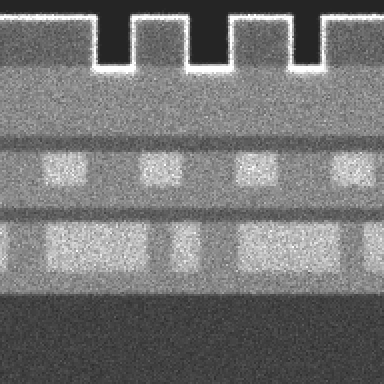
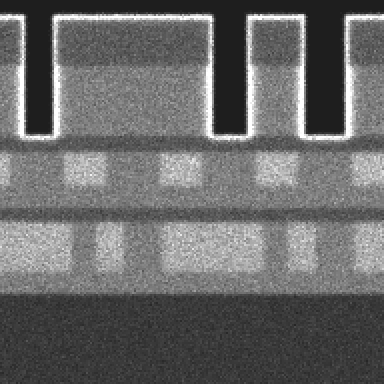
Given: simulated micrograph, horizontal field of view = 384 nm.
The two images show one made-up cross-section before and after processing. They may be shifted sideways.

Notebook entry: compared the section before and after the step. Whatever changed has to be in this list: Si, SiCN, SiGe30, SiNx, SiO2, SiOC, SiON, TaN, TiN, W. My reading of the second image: SiO2 removed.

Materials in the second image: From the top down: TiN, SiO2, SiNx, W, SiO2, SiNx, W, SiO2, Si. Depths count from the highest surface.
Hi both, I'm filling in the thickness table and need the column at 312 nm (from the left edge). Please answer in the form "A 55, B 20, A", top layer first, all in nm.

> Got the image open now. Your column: empty 120, SiNx 16, SiO2 56, SiNx 14, W 50, SiO2 22, Si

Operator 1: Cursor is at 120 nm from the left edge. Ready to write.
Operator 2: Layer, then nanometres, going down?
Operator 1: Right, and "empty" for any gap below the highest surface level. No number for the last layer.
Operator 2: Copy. TiN 50, SiO2 70, SiNx 16, SiO2 56, SiNx 14, W 50, SiO2 22, Si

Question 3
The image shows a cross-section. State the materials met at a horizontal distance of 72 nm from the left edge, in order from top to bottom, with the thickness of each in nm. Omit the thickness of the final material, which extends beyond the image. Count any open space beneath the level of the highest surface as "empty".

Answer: TiN 50, SiO2 70, SiNx 16, W 34, SiO2 22, SiNx 14, SiO2 72, Si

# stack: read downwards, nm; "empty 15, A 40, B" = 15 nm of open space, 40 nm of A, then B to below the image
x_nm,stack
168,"TiN 50, SiO2 70, SiNx 16, W 34, SiO2 22, SiNx 14, W 50, SiO2 22, Si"